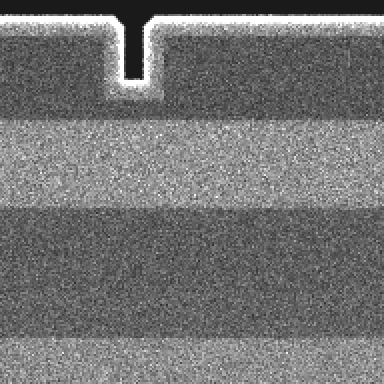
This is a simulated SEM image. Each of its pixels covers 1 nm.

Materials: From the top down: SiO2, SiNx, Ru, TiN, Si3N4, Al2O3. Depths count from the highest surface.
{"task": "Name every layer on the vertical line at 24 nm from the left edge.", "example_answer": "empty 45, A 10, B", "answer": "SiO2 20, SiNx 84, Ru 88, TiN 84, Si3N4 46, Al2O3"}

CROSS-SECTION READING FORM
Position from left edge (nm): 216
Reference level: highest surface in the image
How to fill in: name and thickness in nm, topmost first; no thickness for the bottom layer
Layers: SiO2 20, SiNx 84, Ru 88, TiN 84, Si3N4 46, Al2O3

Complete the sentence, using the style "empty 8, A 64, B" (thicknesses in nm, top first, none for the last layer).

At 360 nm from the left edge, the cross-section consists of SiO2 20, SiNx 84, Ru 88, TiN 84, Si3N4 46, Al2O3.